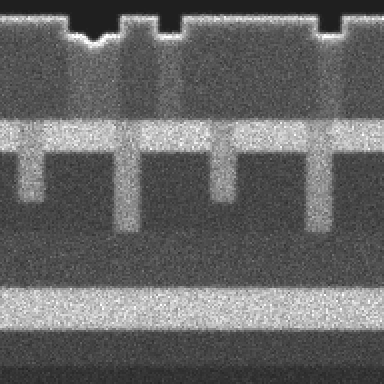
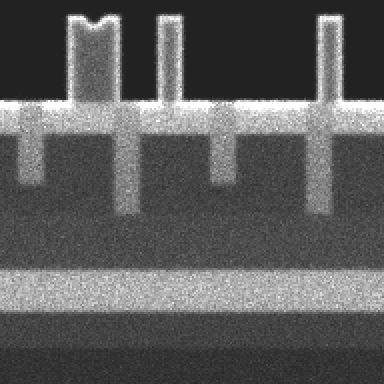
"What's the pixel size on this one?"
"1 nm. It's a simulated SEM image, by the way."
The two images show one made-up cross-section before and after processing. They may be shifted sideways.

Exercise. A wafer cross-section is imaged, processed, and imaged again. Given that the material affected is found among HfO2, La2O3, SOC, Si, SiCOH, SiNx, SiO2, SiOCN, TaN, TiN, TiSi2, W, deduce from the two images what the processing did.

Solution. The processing removed SOC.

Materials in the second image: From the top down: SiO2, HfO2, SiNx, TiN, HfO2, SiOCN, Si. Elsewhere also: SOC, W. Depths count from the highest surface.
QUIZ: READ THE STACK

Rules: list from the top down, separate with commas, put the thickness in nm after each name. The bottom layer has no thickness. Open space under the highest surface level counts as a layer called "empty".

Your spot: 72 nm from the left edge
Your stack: SiO2 86, HfO2 32, SiNx 80, TiN 56, HfO2 42, SiOCN 36, Si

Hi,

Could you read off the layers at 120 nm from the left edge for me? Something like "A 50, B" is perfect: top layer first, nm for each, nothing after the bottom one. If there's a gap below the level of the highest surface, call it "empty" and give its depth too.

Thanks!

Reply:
empty 86, W 112, TiN 56, HfO2 42, SiOCN 36, Si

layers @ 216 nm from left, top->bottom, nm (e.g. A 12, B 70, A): empty 86, W 82, SiNx 30, TiN 56, HfO2 42, SiOCN 36, Si